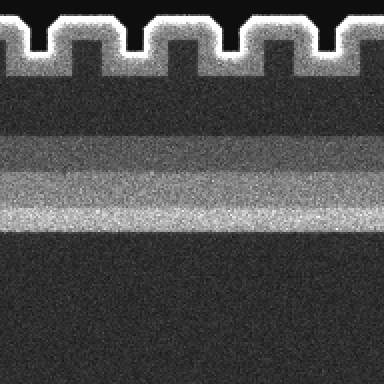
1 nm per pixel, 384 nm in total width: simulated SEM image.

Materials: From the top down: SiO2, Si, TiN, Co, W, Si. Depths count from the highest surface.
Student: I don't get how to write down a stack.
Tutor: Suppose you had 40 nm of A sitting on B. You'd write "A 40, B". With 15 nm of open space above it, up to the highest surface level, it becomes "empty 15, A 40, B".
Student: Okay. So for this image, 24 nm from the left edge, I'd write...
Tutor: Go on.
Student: empty 8, SiO2 52, Si 60, TiN 36, Co 36, W 24, Si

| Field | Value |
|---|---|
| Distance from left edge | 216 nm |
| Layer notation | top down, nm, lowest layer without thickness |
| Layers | empty 8, SiO2 52, Si 60, TiN 36, Co 36, W 24, Si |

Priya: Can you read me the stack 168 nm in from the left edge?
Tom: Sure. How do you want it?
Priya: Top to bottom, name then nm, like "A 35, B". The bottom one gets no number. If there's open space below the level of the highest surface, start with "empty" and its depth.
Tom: SiO2 24, Si 96, TiN 36, Co 36, W 24, Si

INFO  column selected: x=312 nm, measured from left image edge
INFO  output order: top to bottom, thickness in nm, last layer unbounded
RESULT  empty 8, SiO2 52, Si 60, TiN 36, Co 36, W 24, Si